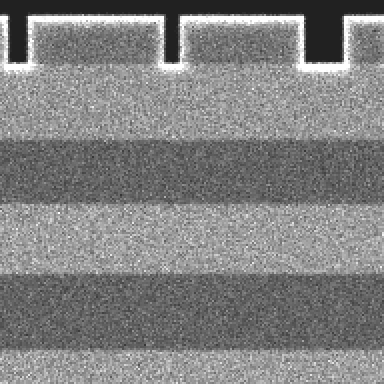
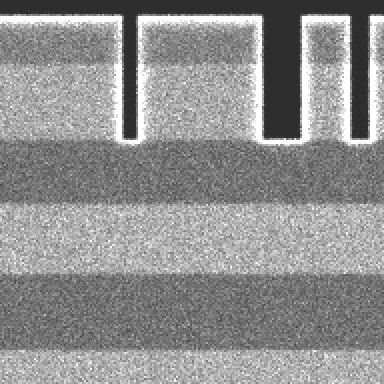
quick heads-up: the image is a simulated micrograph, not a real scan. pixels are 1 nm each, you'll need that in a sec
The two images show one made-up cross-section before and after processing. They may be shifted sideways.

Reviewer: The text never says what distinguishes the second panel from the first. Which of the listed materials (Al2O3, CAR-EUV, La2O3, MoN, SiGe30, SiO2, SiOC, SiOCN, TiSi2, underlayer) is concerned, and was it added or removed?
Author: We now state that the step removed SiO2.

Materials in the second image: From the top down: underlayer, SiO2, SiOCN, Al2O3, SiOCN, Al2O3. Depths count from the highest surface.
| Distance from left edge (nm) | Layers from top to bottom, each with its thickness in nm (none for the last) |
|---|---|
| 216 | underlayer 48, SiO2 76, SiOCN 64, Al2O3 70, SiOCN 76, Al2O3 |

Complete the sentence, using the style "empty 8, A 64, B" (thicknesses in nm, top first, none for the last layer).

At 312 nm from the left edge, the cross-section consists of underlayer 48, SiO2 76, SiOCN 64, Al2O3 70, SiOCN 76, Al2O3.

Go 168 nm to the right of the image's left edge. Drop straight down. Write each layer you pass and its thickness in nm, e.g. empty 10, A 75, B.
underlayer 48, SiO2 76, SiOCN 64, Al2O3 70, SiOCN 76, Al2O3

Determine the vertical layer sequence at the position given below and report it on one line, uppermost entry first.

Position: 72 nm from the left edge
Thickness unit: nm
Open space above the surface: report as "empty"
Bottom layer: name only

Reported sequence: underlayer 48, SiO2 76, SiOCN 64, Al2O3 70, SiOCN 76, Al2O3